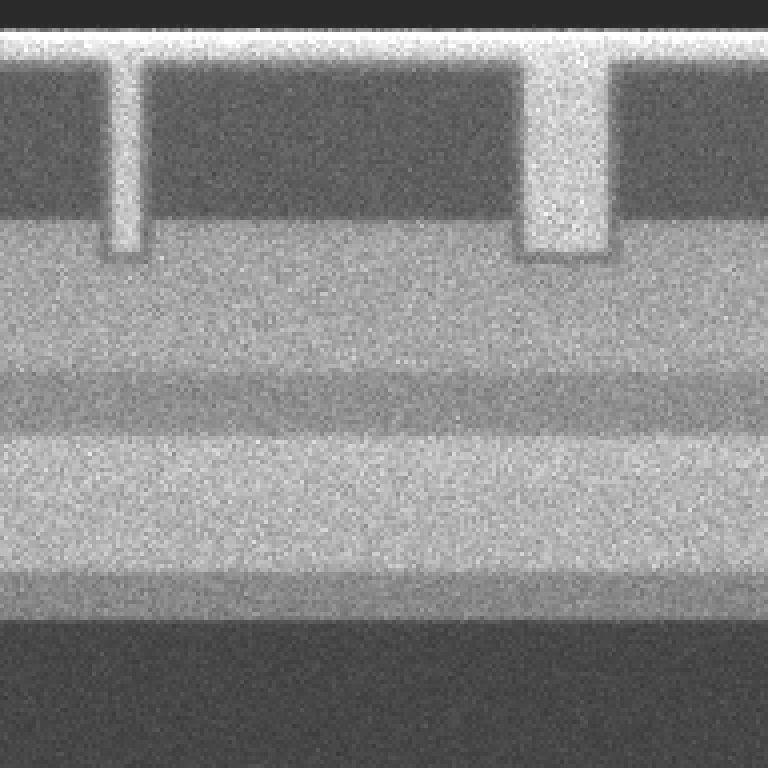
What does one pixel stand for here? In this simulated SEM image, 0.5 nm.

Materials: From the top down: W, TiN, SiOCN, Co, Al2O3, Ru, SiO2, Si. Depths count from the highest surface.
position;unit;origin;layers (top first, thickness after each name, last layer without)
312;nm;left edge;W 14, TiN 6, SiOCN 74, Co 76, Al2O3 32, Ru 68, SiO2 24, Si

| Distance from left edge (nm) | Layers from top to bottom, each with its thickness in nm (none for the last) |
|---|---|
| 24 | W 14, TiN 6, SiOCN 74, Co 76, Al2O3 32, Ru 68, SiO2 24, Si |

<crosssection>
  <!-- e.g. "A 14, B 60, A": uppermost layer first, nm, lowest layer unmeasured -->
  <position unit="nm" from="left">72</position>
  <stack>W 14, TiN 102, Co 54, Al2O3 32, Ru 68, SiO2 24, Si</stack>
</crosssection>